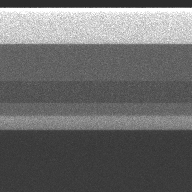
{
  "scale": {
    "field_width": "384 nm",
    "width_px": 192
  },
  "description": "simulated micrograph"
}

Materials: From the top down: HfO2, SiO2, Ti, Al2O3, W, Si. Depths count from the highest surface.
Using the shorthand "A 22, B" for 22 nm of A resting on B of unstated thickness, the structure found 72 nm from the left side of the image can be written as HfO2 72, SiO2 74, Ti 44, Al2O3 26, W 28, Si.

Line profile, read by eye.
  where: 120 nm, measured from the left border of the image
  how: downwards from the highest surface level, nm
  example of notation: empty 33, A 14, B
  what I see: HfO2 72, SiO2 74, Ti 44, Al2O3 26, W 28, Si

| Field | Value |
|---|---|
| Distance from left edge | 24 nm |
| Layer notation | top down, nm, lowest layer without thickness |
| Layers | HfO2 72, SiO2 74, Ti 44, Al2O3 26, W 28, Si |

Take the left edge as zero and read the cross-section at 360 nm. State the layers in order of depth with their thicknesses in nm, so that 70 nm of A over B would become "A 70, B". HfO2 72, SiO2 74, Ti 44, Al2O3 26, W 28, Si